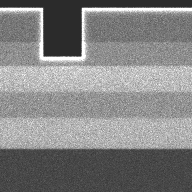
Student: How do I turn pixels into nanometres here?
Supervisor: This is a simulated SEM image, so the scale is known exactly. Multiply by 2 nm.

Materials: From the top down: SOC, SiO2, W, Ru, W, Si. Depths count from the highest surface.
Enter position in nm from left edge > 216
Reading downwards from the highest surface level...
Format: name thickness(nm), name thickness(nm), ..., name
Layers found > SOC 68, SiO2 48, W 52, Ru 52, W 62, Si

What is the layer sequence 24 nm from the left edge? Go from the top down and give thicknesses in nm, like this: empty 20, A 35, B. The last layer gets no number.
SOC 68, SiO2 48, W 52, Ru 52, W 62, Si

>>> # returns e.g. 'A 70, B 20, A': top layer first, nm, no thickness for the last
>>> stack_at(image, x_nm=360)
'SOC 68, SiO2 48, W 52, Ru 52, W 62, Si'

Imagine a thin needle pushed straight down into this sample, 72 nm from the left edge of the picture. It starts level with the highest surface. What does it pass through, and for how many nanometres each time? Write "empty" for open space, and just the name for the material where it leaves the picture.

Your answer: SOC 68, SiO2 48, W 52, Ru 52, W 62, Si